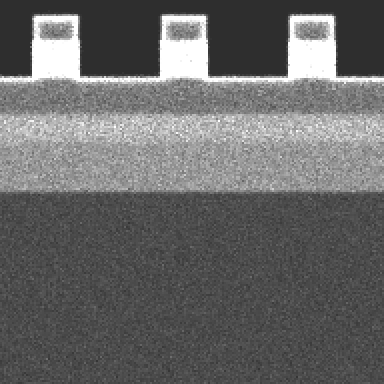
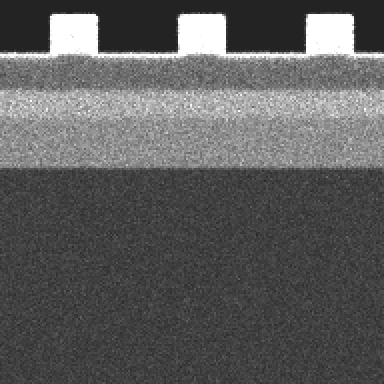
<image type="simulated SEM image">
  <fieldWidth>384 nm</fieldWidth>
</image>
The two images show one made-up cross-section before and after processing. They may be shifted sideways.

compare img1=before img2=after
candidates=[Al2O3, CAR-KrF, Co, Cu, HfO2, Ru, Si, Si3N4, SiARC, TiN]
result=removed:SiARC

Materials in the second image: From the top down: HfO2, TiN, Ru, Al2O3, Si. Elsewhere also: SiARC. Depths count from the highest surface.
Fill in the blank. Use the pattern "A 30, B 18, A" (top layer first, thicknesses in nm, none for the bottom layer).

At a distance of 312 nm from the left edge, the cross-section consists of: HfO2 38, TiN 36, Ru 28, Al2O3 50, Si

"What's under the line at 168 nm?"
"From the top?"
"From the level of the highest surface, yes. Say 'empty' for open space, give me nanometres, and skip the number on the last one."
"empty 38, TiN 36, Ru 28, Al2O3 50, Si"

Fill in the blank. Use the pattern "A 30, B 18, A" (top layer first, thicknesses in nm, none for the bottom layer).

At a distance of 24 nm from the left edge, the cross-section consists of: empty 38, TiN 36, Ru 28, Al2O3 50, Si